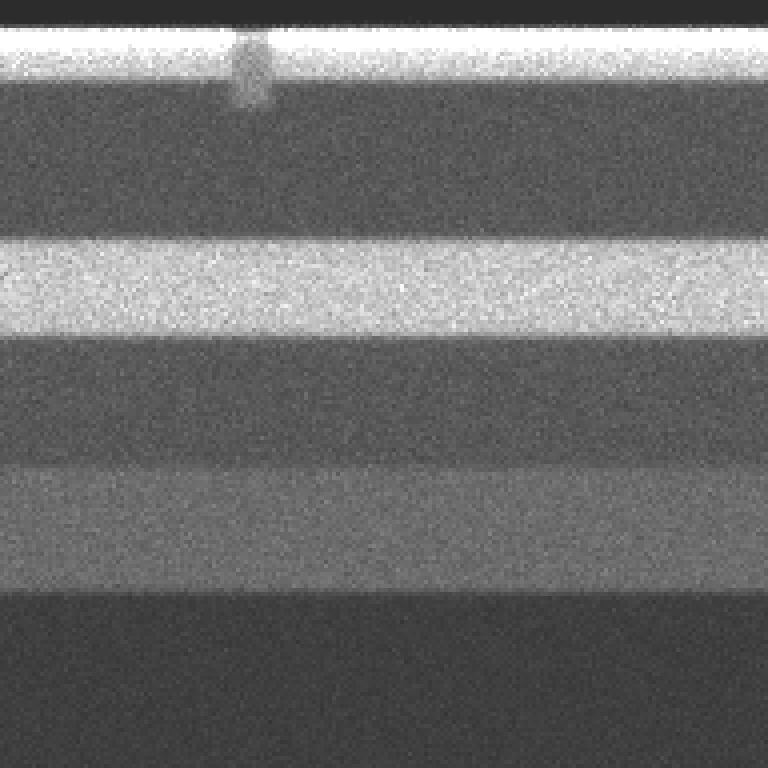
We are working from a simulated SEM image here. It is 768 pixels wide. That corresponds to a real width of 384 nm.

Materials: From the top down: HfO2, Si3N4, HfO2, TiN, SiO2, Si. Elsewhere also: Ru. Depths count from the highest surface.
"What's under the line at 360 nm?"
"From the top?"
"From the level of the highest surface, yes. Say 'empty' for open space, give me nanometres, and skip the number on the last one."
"HfO2 24, Si3N4 80, HfO2 48, TiN 66, SiO2 62, Si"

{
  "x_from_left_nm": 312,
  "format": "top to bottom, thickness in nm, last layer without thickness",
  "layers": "HfO2 24, Si3N4 80, HfO2 48, TiN 66, SiO2 62, Si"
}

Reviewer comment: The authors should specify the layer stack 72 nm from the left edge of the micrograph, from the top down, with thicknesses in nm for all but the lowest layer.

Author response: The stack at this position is HfO2 24, Si3N4 80, HfO2 48, TiN 66, SiO2 62, Si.